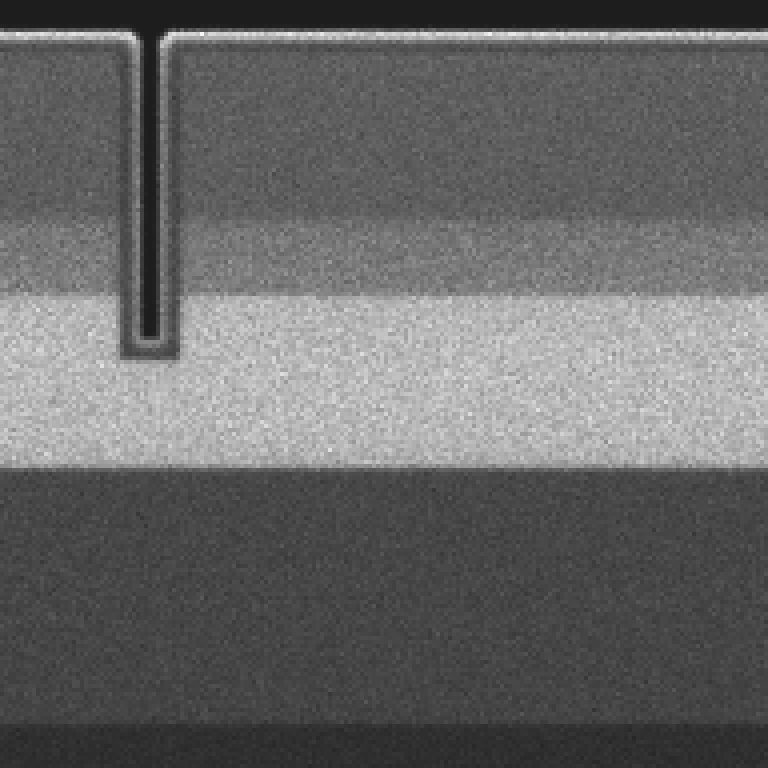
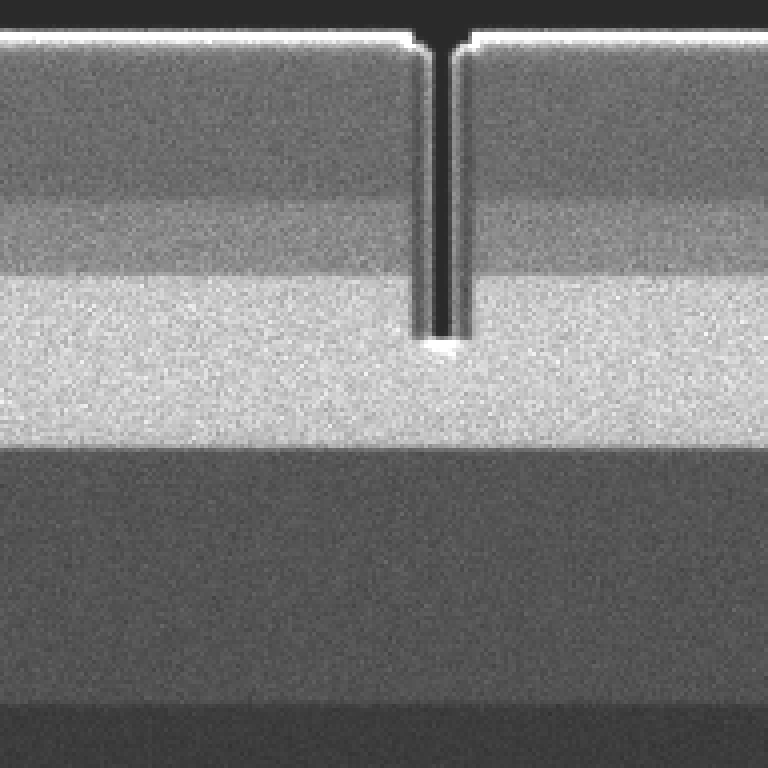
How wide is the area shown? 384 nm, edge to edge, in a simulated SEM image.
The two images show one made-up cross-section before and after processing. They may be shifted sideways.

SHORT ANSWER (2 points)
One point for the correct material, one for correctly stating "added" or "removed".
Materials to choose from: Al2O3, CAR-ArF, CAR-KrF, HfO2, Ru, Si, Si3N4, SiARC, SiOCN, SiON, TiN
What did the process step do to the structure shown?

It removed SiOCN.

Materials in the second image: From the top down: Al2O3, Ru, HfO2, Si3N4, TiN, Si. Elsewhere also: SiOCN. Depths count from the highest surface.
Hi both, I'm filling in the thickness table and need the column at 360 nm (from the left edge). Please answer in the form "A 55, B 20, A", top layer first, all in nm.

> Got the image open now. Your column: Al2O3 84, Ru 38, HfO2 86, Si3N4 42, TiN 86, Si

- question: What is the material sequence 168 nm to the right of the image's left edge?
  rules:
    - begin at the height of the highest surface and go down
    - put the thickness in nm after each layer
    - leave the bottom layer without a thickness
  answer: Al2O3 84, Ru 38, HfO2 86, Si3N4 42, TiN 86, Si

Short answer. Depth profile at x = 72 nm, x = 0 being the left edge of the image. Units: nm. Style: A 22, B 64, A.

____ Al2O3 84, Ru 38, HfO2 86, Si3N4 42, TiN 86, Si